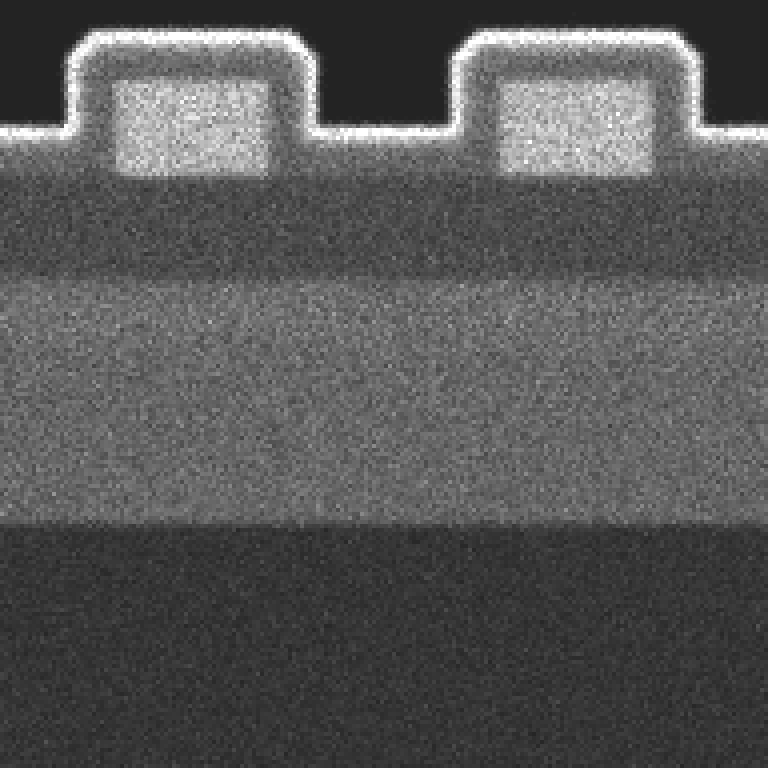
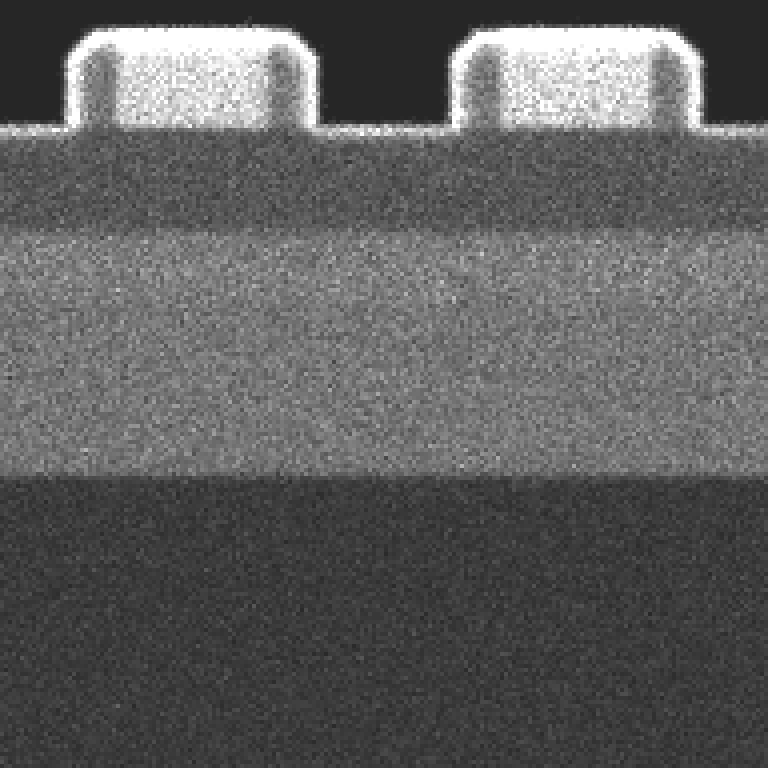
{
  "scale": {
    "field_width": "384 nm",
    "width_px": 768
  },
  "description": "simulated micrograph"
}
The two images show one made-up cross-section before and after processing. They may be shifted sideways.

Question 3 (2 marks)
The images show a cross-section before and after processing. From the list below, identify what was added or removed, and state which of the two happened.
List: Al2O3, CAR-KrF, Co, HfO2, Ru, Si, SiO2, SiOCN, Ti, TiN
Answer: SiO2 was removed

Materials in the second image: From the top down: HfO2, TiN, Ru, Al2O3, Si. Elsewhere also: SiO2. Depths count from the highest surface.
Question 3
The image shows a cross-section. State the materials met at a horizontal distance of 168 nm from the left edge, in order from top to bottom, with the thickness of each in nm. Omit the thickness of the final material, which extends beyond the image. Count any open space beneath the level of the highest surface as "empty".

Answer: empty 48, TiN 52, Ru 34, Al2O3 88, Si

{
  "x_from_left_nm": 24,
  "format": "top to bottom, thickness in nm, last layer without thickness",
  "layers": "empty 48, TiN 52, Ru 34, Al2O3 88, Si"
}